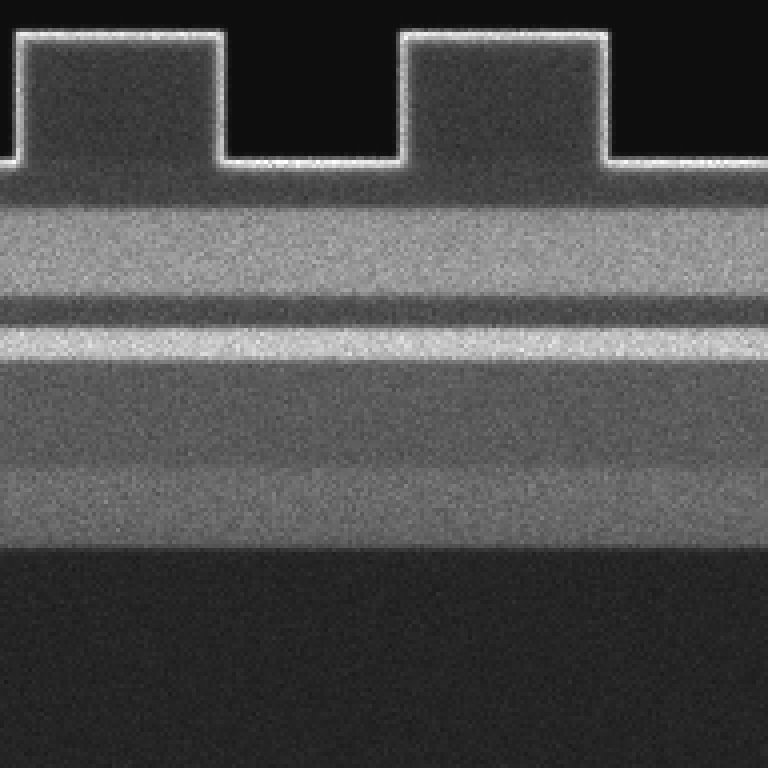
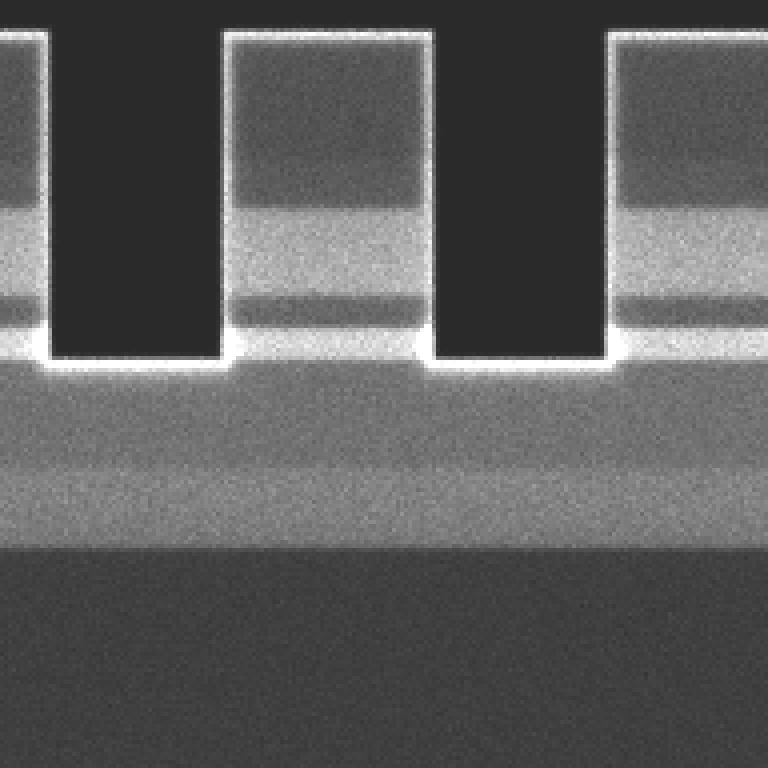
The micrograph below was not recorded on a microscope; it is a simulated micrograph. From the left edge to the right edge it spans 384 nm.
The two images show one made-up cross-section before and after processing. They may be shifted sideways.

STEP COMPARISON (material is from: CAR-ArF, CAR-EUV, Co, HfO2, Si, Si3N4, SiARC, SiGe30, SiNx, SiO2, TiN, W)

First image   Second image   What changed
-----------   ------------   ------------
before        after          HfO2 and Si3N4 and TiN and W, removed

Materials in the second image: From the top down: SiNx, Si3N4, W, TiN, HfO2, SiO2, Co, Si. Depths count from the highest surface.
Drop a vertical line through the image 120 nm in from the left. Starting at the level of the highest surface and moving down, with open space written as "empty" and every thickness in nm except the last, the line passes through SiNx 64, Si3N4 24, W 44, TiN 16, HfO2 16, SiO2 54, Co 40, Si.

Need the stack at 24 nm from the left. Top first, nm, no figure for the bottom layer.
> empty 164, SiO2 54, Co 40, Si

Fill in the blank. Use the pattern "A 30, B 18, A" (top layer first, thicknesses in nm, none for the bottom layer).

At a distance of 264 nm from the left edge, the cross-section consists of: empty 164, SiO2 54, Co 40, Si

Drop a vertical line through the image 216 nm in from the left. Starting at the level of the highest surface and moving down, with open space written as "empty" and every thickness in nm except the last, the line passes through empty 164, SiO2 54, Co 40, Si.